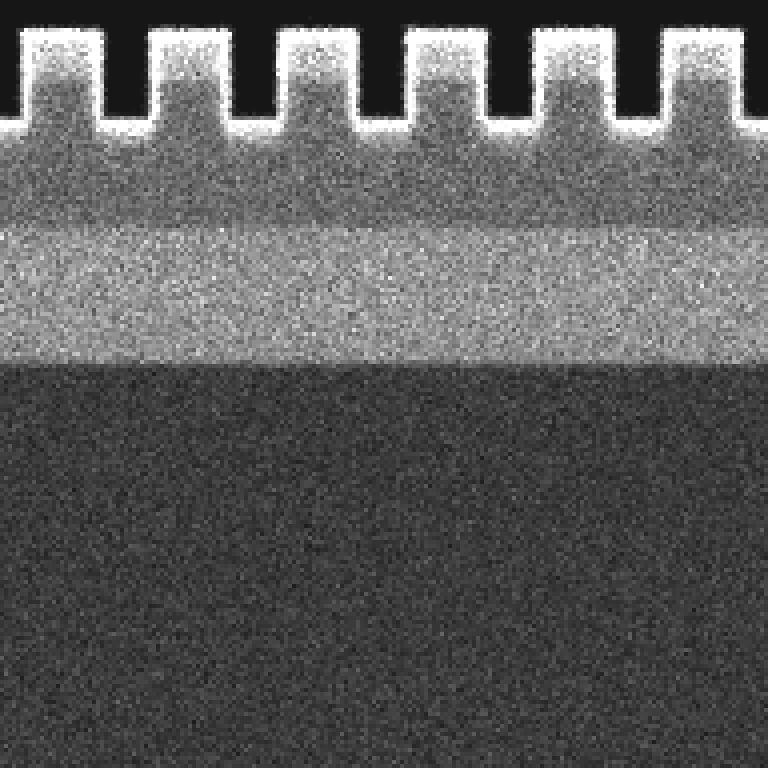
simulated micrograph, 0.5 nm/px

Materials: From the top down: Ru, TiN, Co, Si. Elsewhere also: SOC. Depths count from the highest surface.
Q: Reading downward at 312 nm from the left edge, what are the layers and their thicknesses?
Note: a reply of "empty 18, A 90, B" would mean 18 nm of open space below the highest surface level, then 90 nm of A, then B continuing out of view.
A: empty 44, SOC 14, TiN 40, Co 68, Si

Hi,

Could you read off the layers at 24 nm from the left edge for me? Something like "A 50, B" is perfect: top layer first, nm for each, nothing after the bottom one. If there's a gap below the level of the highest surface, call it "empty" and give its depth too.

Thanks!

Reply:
Ru 24, TiN 74, Co 68, Si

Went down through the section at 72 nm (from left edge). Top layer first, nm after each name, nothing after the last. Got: empty 44, SOC 14, TiN 40, Co 68, Si